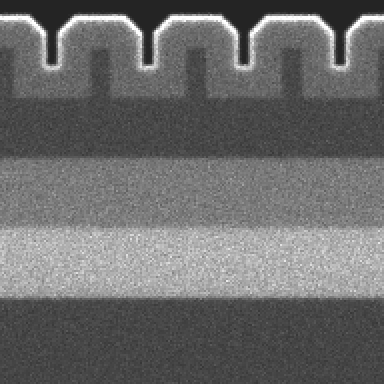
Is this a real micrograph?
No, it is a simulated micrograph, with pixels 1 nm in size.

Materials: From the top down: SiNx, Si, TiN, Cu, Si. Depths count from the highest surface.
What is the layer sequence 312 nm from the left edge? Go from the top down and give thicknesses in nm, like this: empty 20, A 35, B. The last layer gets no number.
SiNx 82, Si 60, TiN 70, Cu 70, Si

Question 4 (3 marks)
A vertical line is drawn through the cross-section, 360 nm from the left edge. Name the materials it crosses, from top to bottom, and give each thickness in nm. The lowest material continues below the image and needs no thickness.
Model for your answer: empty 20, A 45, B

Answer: empty 2, SiNx 80, Si 60, TiN 70, Cu 70, Si